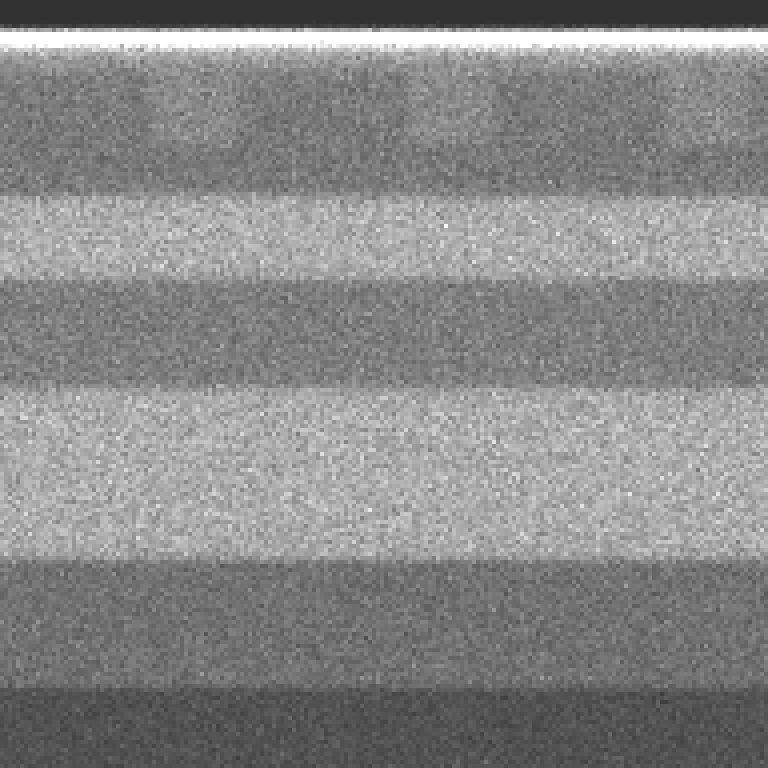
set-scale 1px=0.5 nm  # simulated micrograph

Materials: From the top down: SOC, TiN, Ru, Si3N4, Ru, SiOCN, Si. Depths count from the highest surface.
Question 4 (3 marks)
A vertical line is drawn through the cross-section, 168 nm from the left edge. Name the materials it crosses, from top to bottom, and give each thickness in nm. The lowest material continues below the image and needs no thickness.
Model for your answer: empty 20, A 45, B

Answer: SOC 20, TiN 62, Ru 42, Si3N4 54, Ru 86, SiOCN 64, Si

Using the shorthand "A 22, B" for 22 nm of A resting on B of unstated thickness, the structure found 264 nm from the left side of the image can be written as SOC 20, TiN 62, Ru 42, Si3N4 54, Ru 86, SiOCN 64, Si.